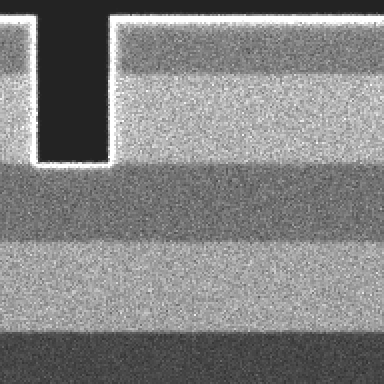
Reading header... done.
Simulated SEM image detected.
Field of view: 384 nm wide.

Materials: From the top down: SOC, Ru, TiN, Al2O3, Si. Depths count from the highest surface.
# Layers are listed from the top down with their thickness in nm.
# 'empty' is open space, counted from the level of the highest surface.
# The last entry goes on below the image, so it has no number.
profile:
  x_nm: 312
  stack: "SOC 58, Ru 90, TiN 78, Al2O3 90, Si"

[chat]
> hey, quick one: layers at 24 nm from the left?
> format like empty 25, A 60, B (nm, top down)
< SOC 58, Ru 90, TiN 78, Al2O3 90, Si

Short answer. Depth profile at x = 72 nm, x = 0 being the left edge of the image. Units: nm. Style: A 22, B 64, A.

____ empty 148, TiN 78, Al2O3 90, Si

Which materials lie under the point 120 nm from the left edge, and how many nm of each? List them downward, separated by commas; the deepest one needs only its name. SOC 58, Ru 90, TiN 78, Al2O3 90, Si